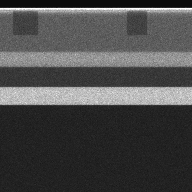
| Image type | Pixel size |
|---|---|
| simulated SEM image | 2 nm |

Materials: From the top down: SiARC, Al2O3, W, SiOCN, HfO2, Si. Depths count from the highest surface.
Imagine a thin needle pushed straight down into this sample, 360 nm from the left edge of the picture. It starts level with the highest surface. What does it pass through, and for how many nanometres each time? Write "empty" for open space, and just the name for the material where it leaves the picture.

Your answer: SiARC 6, Al2O3 82, W 30, SiOCN 40, HfO2 36, Si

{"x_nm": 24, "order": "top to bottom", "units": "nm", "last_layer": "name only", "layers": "SiARC 6, Al2O3 82, W 30, SiOCN 40, HfO2 36, Si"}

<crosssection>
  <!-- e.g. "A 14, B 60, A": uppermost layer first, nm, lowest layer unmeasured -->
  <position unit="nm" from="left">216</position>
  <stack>SiARC 6, Al2O3 82, W 30, SiOCN 40, HfO2 36, Si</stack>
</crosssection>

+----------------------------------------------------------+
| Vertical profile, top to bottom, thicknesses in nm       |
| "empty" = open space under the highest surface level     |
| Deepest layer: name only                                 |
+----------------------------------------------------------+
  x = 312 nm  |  SiARC 6, Al2O3 82, W 30, SiOCN 40, HfO2 36, Si